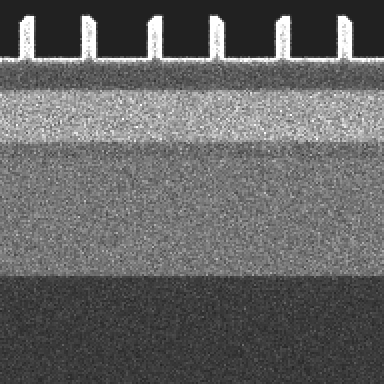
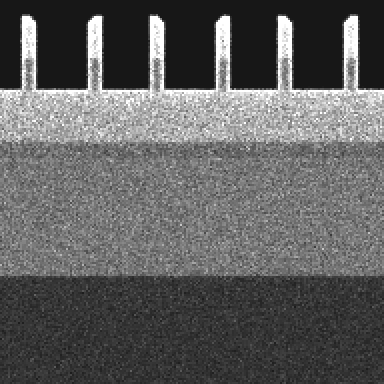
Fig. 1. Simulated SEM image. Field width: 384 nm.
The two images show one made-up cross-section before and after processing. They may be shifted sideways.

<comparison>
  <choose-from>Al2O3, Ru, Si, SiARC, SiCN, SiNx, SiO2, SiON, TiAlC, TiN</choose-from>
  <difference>SiNx removed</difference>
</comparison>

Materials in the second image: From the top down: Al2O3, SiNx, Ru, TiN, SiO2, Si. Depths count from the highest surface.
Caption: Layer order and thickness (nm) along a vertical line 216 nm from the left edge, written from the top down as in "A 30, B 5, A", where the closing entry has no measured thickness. empty 6, Al2O3 36, SiNx 32, Ru 52, TiN 16, SiO2 118, Si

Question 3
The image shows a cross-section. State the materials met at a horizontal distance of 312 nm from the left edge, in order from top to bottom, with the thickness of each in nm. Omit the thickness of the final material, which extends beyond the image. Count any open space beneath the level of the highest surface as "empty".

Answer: empty 74, Ru 52, TiN 16, SiO2 118, Si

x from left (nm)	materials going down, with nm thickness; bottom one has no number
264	empty 74, Ru 52, TiN 16, SiO2 118, Si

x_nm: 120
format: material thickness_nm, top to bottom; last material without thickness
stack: empty 74, Ru 52, TiN 16, SiO2 118, Si